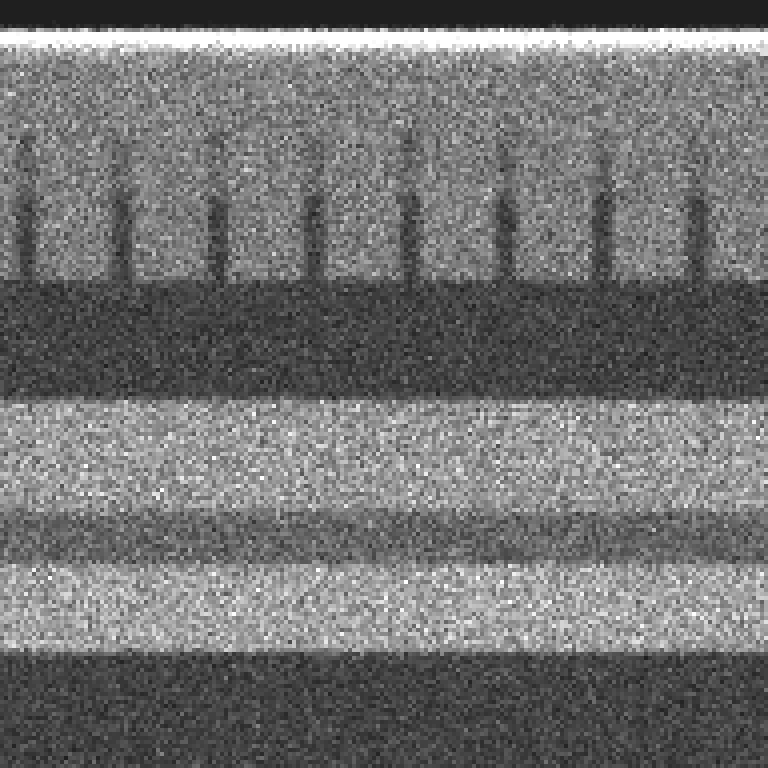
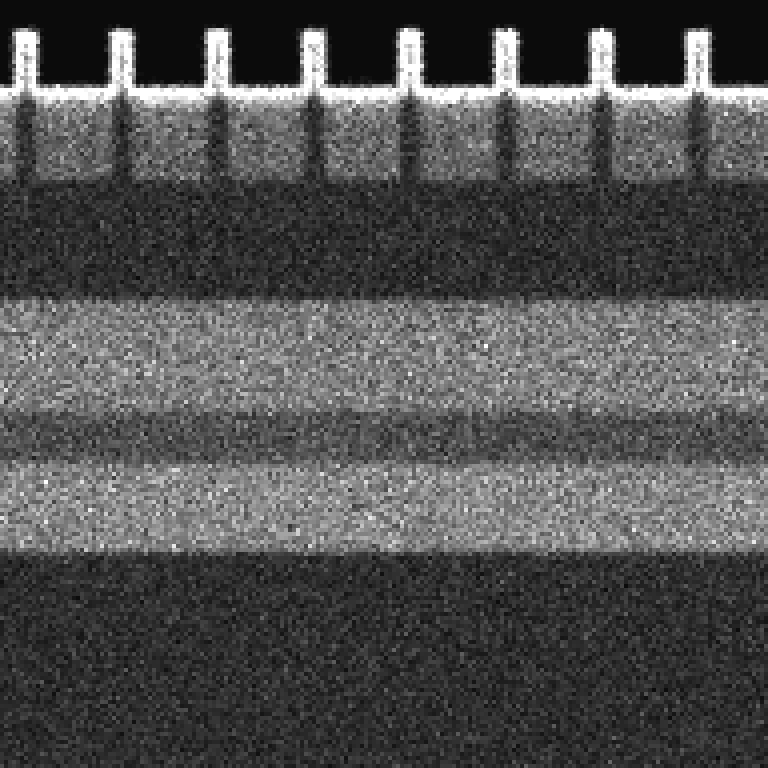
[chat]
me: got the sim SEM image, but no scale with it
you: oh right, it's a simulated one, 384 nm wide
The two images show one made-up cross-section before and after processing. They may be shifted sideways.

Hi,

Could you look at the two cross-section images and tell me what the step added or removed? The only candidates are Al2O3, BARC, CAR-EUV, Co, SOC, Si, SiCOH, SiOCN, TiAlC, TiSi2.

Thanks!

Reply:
removed SOC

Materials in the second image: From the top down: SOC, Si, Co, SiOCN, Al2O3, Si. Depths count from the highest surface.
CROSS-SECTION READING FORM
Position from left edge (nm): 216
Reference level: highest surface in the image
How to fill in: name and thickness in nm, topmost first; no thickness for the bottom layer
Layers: empty 28, SOC 46, Si 60, Co 56, SiOCN 26, Al2O3 44, Si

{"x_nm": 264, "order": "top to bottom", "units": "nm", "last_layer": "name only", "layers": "empty 28, SOC 46, Si 60, Co 56, SiOCN 26, Al2O3 44, Si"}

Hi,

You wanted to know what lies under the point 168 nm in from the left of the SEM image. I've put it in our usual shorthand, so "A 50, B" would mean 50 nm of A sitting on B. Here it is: empty 28, SOC 46, Si 60, Co 56, SiOCN 26, Al2O3 44, Si